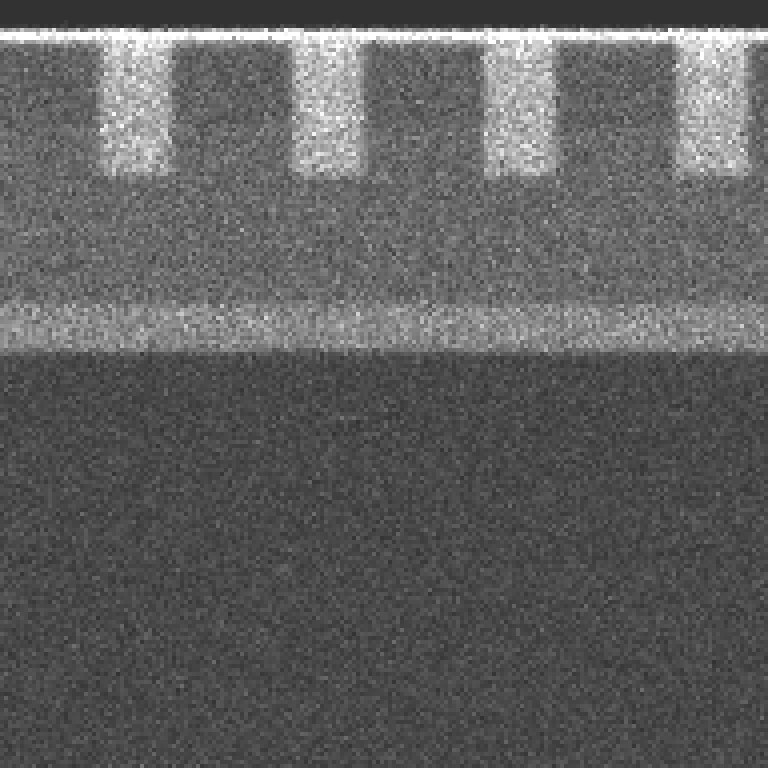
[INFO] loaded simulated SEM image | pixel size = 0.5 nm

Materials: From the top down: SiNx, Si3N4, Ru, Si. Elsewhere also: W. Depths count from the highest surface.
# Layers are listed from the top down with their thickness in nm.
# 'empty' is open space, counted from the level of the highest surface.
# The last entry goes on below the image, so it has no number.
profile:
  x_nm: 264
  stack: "W 72, Si3N4 64, Ru 24, Si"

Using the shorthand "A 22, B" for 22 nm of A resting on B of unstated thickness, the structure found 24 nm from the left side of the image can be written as SiNx 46, Si3N4 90, Ru 24, Si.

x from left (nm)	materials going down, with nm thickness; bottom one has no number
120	SiNx 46, Si3N4 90, Ru 24, Si